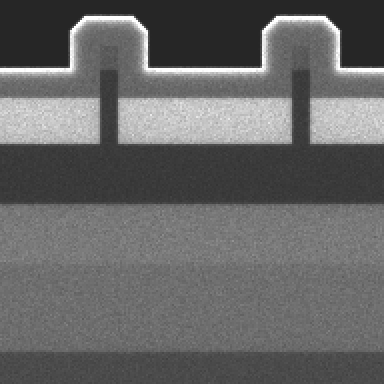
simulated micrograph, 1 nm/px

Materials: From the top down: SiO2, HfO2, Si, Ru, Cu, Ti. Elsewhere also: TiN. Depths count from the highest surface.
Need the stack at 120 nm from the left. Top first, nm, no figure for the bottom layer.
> SiO2 82, HfO2 46, Si 60, Ru 60, Cu 88, Ti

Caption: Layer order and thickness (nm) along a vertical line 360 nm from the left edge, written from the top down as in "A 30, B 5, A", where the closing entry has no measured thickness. empty 52, SiO2 30, HfO2 46, Si 60, Ru 60, Cu 88, Ti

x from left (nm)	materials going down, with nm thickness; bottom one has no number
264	empty 12, SiO2 70, HfO2 46, Si 60, Ru 60, Cu 88, Ti